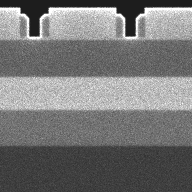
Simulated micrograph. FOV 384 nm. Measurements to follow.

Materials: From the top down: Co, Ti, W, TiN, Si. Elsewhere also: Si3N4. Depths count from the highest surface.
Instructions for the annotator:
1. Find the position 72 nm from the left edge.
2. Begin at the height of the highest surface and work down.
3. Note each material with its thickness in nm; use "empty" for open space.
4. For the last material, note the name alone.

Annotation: empty 58, Co 6, Ti 74, W 66, TiN 72, Si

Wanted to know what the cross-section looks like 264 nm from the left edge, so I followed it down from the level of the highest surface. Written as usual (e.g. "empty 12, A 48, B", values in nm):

empty 58, Co 6, Ti 74, W 66, TiN 72, Si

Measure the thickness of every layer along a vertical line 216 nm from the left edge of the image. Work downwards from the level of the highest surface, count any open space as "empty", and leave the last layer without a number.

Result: Co 64, Ti 74, W 66, TiN 72, Si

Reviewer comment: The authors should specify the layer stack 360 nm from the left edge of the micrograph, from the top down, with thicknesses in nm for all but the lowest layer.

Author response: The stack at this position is Co 64, Ti 74, W 66, TiN 72, Si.